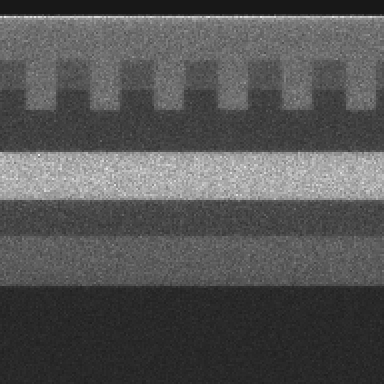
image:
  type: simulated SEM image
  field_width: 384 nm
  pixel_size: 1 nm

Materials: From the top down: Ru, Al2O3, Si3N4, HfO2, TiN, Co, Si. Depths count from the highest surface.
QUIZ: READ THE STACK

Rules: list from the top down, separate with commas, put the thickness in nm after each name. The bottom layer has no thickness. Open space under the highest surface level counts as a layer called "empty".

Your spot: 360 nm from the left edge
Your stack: Ru 94, Si3N4 42, HfO2 48, TiN 36, Co 50, Si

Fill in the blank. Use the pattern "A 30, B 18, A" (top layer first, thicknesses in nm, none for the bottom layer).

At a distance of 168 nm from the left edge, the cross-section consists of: Ru 94, Si3N4 42, HfO2 48, TiN 36, Co 50, Si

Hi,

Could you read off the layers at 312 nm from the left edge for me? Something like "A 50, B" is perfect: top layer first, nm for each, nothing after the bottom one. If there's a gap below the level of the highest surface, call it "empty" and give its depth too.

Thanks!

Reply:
Ru 44, Al2O3 30, Si3N4 62, HfO2 48, TiN 36, Co 50, Si